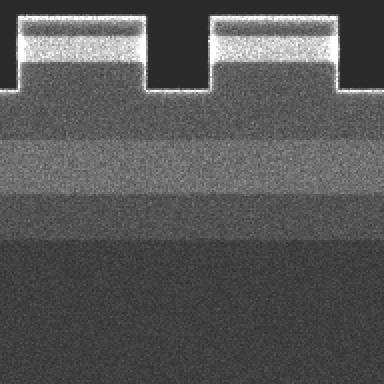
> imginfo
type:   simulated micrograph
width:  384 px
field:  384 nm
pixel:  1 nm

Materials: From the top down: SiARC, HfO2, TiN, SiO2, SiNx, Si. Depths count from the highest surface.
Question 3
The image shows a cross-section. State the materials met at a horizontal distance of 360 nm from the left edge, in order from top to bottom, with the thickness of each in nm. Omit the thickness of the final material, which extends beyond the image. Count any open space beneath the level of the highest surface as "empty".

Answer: empty 74, TiN 50, SiO2 54, SiNx 46, Si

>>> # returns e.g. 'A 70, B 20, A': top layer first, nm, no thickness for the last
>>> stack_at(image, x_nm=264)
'SiARC 20, HfO2 26, TiN 78, SiO2 54, SiNx 46, Si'